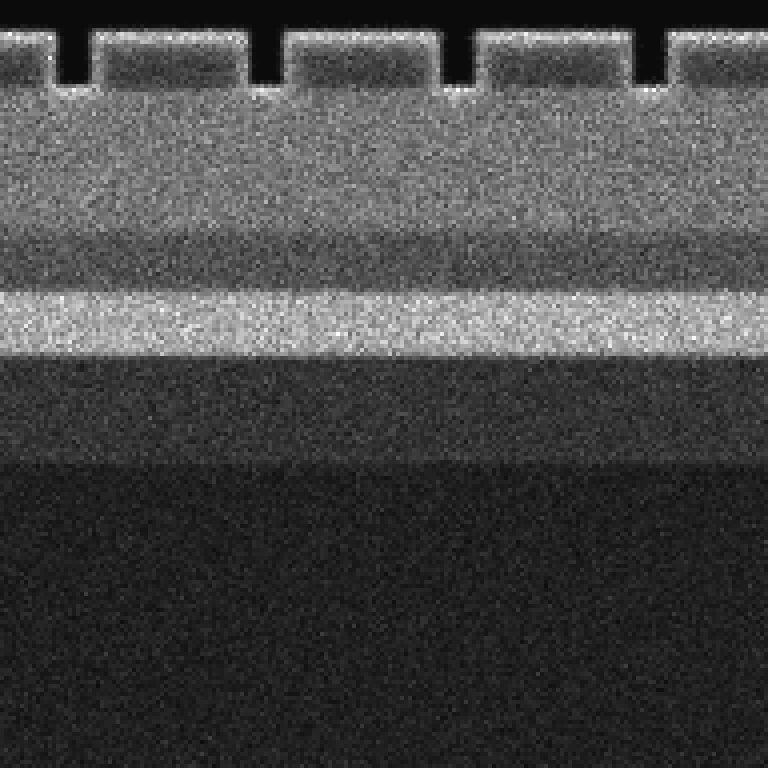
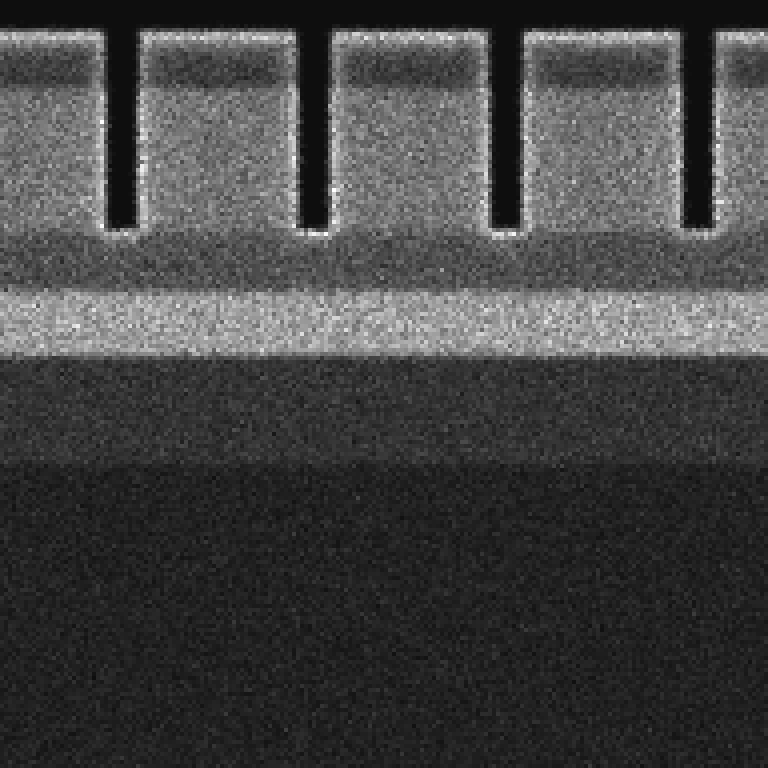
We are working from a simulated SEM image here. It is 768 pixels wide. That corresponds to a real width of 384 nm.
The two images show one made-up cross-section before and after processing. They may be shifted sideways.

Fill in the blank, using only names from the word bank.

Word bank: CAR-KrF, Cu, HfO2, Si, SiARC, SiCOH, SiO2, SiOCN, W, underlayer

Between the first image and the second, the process removed W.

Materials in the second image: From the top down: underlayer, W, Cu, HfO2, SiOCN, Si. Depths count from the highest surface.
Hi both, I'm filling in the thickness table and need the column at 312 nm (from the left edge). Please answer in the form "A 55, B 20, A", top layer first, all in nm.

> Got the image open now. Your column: underlayer 28, W 72, Cu 30, HfO2 32, SiOCN 54, Si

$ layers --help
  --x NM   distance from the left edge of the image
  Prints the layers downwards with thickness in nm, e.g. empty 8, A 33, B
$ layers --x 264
underlayer 28, W 72, Cu 30, HfO2 32, SiOCN 54, Si